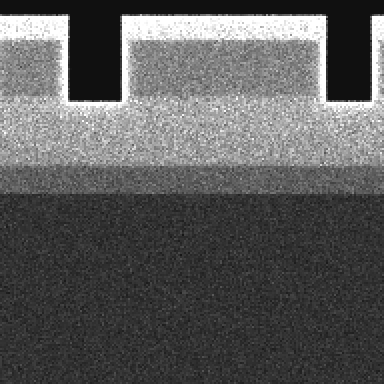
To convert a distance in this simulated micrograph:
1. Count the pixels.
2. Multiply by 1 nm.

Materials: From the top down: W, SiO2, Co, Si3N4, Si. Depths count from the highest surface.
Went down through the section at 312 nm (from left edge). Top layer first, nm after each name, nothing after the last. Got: W 24, SiO2 56, Co 70, Si3N4 28, Si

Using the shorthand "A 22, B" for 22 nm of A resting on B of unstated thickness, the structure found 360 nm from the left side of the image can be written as empty 86, Co 64, Si3N4 28, Si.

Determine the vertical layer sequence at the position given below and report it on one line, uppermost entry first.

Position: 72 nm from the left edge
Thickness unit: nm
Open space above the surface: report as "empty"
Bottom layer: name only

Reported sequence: empty 86, Co 64, Si3N4 28, Si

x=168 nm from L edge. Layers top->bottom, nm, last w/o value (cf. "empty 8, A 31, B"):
W 24, SiO2 56, Co 70, Si3N4 28, Si